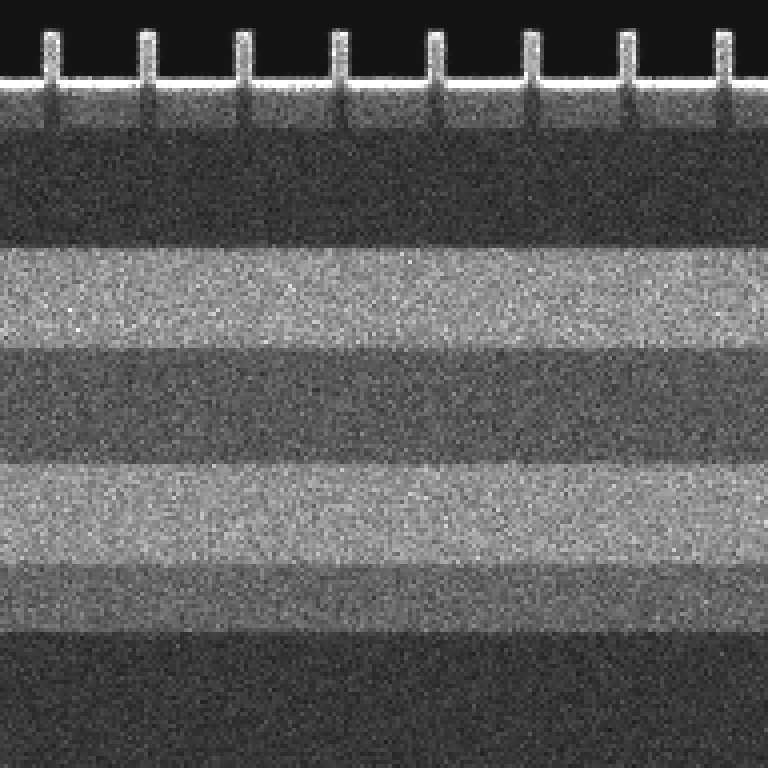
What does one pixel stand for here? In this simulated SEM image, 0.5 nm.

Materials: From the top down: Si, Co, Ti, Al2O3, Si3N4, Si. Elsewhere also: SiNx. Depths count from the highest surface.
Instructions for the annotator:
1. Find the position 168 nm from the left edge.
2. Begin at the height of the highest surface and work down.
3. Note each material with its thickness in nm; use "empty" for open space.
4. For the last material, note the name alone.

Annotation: Si 108, Co 50, Ti 58, Al2O3 50, Si3N4 34, Si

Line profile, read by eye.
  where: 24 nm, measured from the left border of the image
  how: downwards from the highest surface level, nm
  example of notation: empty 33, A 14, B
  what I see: Si 108, Co 50, Ti 58, Al2O3 50, Si3N4 34, Si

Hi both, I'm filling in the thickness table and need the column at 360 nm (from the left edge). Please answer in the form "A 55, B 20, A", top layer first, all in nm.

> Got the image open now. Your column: Si 108, Co 50, Ti 58, Al2O3 50, Si3N4 34, Si